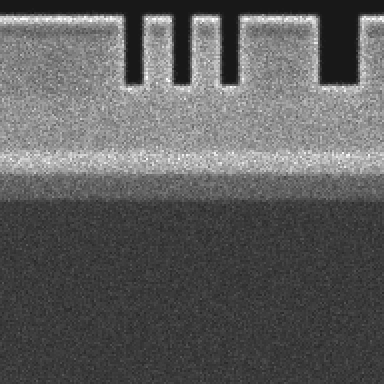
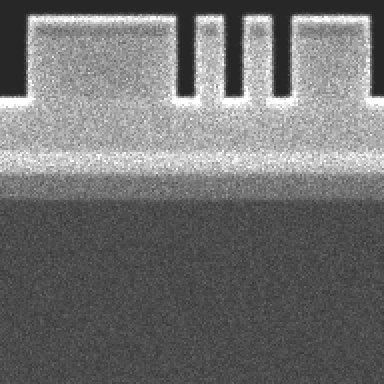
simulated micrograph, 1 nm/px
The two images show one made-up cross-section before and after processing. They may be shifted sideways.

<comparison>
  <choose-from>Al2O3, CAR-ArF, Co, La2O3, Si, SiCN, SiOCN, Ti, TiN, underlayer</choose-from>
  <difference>TiN removed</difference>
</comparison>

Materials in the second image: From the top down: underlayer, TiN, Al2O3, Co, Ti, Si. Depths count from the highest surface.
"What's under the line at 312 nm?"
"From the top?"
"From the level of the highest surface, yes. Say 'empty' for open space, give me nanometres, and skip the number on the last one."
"underlayer 20, TiN 62, Al2O3 54, Co 22, Ti 26, Si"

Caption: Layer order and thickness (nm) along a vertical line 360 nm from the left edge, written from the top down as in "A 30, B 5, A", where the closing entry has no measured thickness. underlayer 20, TiN 62, Al2O3 54, Co 22, Ti 26, Si